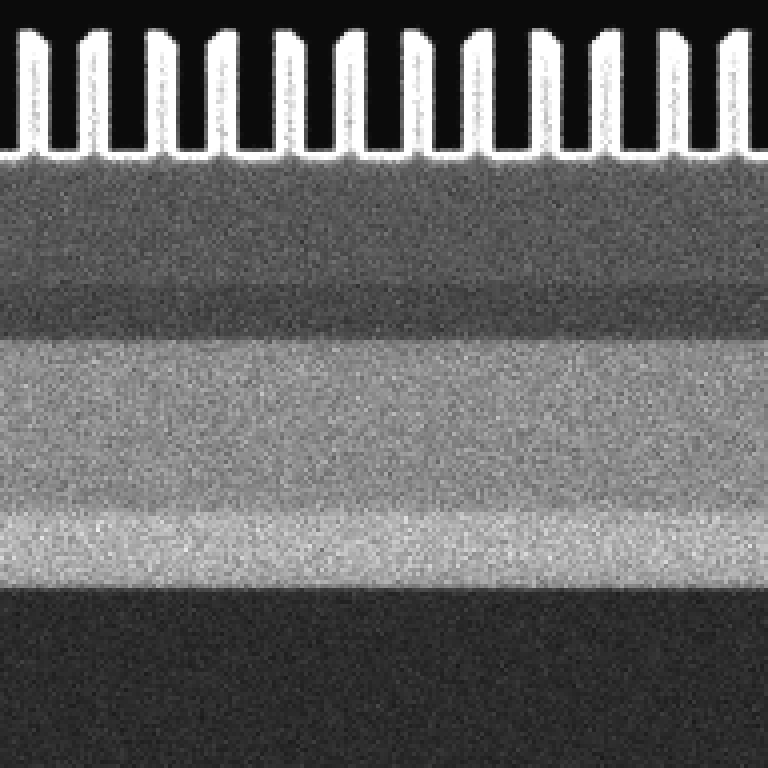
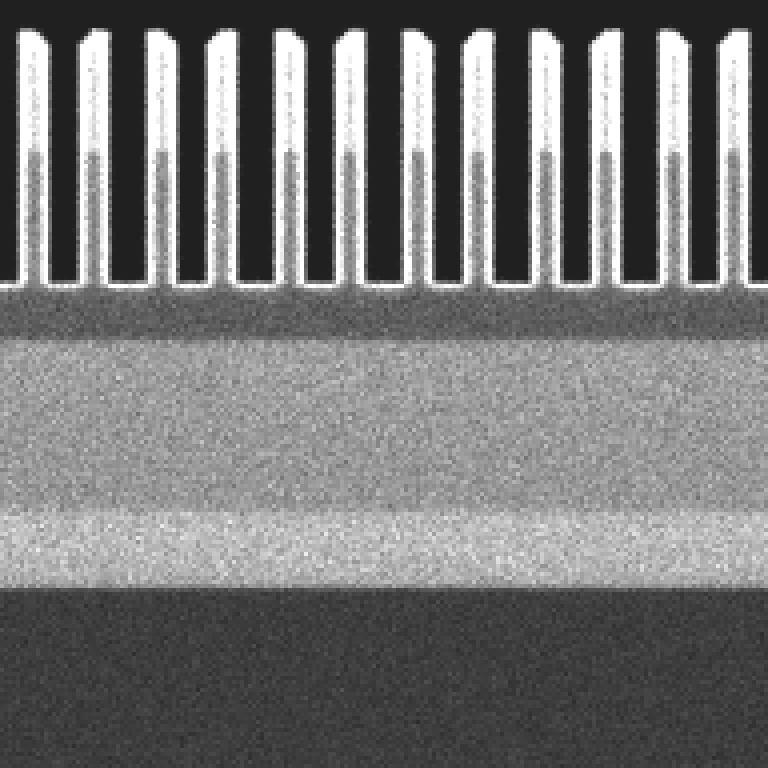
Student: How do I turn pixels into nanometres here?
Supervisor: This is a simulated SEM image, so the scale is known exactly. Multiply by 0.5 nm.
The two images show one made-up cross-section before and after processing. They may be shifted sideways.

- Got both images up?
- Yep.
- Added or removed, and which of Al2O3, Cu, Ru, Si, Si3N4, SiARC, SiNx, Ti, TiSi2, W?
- removed, Si3N4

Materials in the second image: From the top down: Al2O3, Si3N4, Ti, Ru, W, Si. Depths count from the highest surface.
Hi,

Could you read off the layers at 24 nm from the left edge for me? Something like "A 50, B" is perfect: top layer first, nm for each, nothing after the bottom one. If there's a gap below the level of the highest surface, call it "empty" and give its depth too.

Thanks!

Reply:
empty 126, Ti 28, Ru 86, W 38, Si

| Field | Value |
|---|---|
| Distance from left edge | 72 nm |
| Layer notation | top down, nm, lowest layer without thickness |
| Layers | empty 126, Ti 28, Ru 86, W 38, Si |